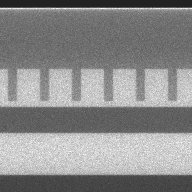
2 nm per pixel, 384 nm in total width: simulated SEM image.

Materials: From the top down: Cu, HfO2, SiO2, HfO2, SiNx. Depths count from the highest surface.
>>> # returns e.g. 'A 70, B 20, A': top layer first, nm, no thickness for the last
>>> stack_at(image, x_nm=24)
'Cu 186, HfO2 12, SiO2 52, HfO2 84, SiNx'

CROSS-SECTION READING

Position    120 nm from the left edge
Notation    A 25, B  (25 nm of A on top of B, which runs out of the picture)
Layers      Cu 122, HfO2 76, SiO2 52, HfO2 84, SiNx